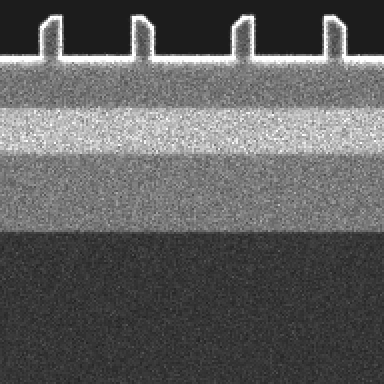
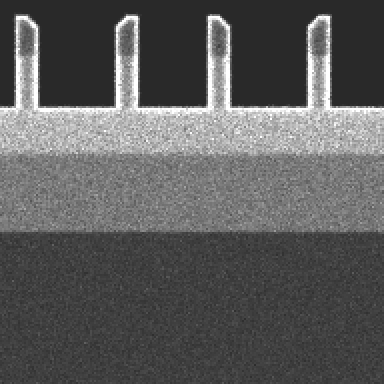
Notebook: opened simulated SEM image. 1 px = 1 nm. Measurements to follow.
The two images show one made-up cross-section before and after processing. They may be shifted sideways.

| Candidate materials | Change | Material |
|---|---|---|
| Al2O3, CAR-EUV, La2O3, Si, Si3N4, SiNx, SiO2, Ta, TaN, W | removed | SiO2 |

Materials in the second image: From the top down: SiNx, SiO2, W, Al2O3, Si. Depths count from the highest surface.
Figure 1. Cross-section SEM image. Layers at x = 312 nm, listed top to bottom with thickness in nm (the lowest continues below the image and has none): empty 6, SiNx 34, SiO2 52, W 46, Al2O3 78, Si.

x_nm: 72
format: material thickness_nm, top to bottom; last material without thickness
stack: empty 92, W 46, Al2O3 78, Si